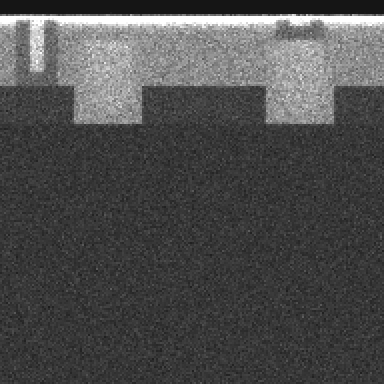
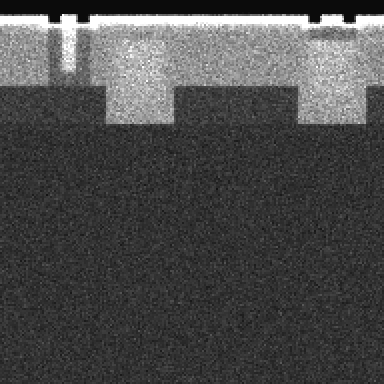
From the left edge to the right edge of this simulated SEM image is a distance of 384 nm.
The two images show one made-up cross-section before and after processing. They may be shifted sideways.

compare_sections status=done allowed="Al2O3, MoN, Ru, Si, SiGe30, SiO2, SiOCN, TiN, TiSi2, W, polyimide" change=removed material="TiN"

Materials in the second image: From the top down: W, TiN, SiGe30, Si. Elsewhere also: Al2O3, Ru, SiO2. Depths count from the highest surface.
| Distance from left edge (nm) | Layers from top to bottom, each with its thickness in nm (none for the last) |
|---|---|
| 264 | SiO2 70, SiGe30 38, Si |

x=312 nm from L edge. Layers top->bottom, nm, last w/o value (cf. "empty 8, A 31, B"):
empty 8, TiN 16, Ru 72, Al2O3 12, Si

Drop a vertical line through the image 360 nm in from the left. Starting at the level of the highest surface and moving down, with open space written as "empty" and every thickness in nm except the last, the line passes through SiO2 24, Al2O3 84, Si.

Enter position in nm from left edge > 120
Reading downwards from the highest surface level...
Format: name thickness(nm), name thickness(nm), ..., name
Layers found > SiO2 24, Ru 72, Al2O3 12, Si